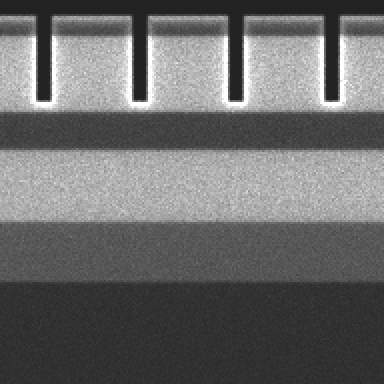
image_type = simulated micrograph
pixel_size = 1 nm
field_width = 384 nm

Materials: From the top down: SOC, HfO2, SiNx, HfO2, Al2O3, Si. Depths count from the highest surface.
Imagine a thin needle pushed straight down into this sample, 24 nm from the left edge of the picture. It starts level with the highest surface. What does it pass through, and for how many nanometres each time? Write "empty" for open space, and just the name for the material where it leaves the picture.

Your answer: SOC 20, HfO2 76, SiNx 38, HfO2 72, Al2O3 60, Si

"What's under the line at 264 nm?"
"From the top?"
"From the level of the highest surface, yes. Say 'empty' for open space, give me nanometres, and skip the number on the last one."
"SOC 20, HfO2 76, SiNx 38, HfO2 72, Al2O3 60, Si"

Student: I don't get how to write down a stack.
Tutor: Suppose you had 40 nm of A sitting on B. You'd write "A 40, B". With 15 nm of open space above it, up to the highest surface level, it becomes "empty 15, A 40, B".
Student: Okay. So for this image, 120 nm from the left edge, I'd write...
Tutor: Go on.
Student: SOC 20, HfO2 76, SiNx 38, HfO2 72, Al2O3 60, Si